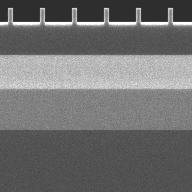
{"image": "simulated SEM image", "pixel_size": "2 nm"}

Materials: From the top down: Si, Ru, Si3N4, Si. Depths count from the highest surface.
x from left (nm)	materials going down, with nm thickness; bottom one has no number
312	empty 28, Si 66, Ru 68, Si3N4 82, Si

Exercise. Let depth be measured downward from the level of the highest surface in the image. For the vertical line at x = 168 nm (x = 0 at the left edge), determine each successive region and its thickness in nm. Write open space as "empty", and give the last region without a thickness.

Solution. empty 28, Si 66, Ru 68, Si3N4 82, Si